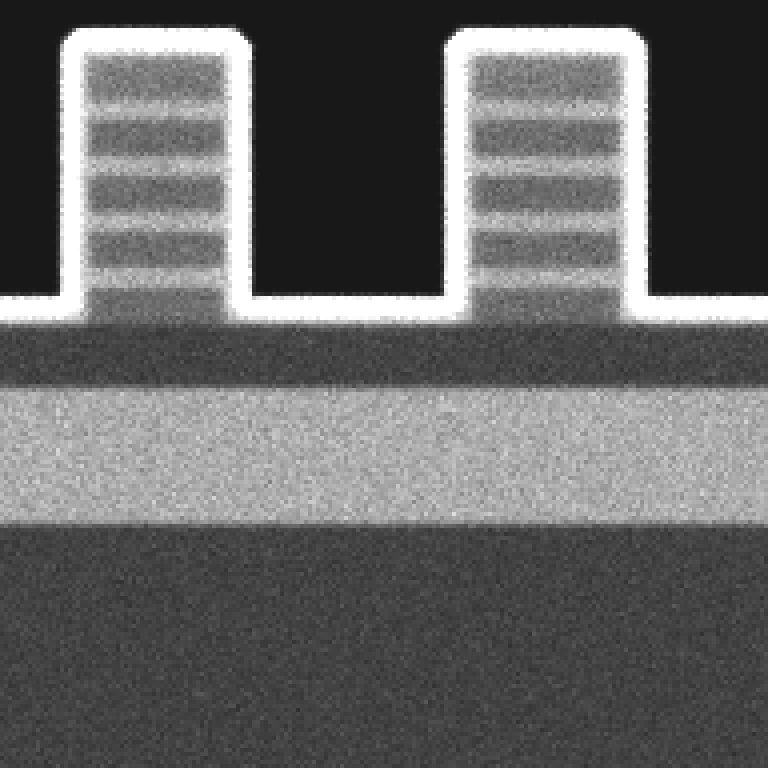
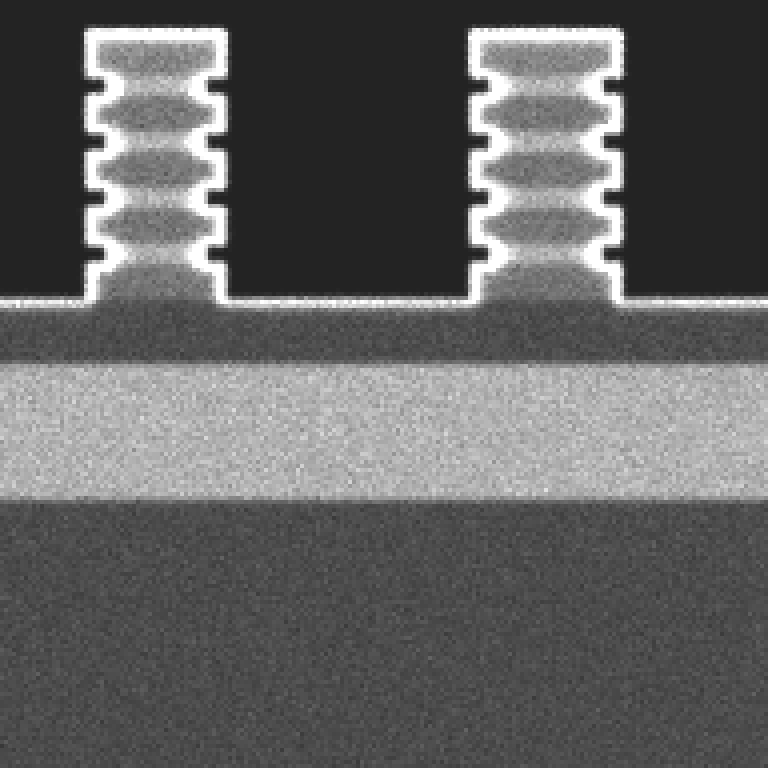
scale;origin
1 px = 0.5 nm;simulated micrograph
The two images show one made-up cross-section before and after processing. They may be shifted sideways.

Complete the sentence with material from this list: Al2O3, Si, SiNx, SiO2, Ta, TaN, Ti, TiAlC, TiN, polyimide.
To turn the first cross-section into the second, Al2O3 must be removed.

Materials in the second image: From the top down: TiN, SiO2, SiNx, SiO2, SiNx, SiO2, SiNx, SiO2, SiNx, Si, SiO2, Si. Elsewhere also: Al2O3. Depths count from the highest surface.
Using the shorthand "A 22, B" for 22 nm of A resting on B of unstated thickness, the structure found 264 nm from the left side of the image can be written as TiN 22, SiO2 10, SiNx 18, SiO2 10, SiNx 18, SiO2 10, SiNx 18, SiO2 10, SiNx 18, Si 32, SiO2 68, Si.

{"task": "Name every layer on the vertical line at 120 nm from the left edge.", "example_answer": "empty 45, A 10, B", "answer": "empty 134, Si 32, SiO2 68, Si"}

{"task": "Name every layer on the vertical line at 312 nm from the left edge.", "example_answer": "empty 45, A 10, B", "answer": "empty 134, Si 32, SiO2 68, Si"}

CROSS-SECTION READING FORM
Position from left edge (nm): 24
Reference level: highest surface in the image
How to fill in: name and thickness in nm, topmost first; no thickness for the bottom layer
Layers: empty 134, Si 32, SiO2 68, Si